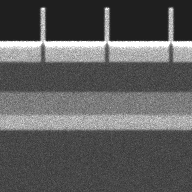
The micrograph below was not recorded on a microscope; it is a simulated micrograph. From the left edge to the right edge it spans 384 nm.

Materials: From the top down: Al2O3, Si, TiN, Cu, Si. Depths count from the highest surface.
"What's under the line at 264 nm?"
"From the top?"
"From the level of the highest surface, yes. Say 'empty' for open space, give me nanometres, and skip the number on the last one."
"empty 68, Al2O3 40, Si 60, TiN 46, Cu 30, Si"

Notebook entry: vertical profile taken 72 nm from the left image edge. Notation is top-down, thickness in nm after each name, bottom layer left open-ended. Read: empty 68, Al2O3 40, Si 60, TiN 46, Cu 30, Si